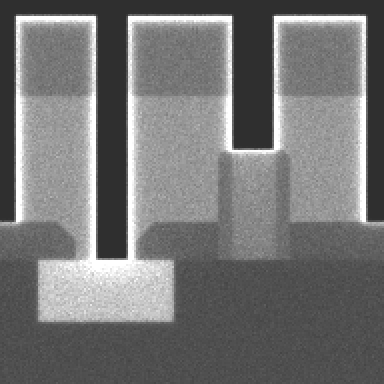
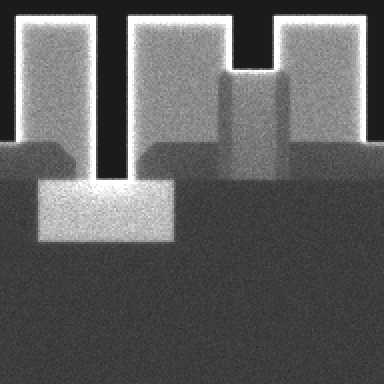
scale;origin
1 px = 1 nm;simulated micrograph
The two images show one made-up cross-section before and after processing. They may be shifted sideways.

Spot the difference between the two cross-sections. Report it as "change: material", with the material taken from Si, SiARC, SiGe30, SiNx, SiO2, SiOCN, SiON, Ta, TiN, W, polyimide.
removed: SiARC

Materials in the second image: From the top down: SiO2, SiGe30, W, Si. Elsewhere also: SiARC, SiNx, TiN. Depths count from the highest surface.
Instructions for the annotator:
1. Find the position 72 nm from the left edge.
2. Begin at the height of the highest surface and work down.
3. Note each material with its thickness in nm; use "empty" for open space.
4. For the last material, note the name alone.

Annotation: SiO2 142, SiGe30 22, W 62, Si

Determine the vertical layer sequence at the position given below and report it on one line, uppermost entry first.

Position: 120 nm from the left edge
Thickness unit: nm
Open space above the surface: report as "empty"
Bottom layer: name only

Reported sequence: empty 164, W 62, Si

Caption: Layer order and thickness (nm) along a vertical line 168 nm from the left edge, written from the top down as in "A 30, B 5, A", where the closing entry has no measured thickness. SiO2 126, SiGe30 38, W 62, Si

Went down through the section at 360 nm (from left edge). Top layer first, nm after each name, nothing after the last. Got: SiO2 126, SiGe30 38, Si